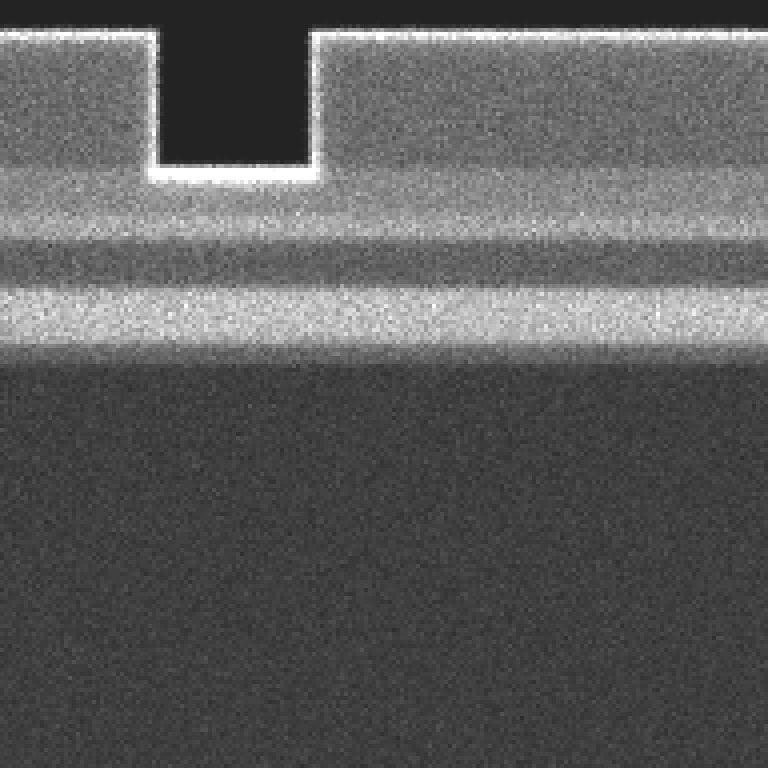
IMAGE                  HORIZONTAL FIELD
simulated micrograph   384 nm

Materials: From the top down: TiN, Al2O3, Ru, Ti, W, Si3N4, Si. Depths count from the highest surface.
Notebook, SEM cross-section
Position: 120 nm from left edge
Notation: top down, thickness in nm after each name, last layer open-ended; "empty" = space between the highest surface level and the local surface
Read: empty 68, Al2O3 24, Ru 12, Ti 24, W 28, Si3N4 10, Si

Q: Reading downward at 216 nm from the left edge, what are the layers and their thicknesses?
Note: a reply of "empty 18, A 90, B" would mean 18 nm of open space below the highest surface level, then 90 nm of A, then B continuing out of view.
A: TiN 68, Al2O3 24, Ru 12, Ti 24, W 28, Si3N4 10, Si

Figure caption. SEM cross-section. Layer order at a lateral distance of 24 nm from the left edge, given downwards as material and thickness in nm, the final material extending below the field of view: TiN 68, Al2O3 24, Ru 12, Ti 24, W 28, Si3N4 10, Si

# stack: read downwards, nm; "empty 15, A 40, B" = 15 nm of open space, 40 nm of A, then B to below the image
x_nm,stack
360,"TiN 68, Al2O3 24, Ru 12, Ti 24, W 28, Si3N4 10, Si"